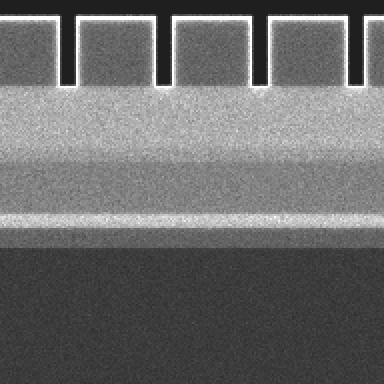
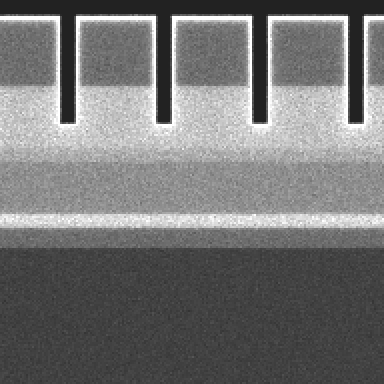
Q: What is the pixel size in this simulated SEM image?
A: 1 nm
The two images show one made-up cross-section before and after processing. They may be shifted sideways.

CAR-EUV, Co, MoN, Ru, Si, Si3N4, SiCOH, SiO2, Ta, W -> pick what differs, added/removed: Ru removed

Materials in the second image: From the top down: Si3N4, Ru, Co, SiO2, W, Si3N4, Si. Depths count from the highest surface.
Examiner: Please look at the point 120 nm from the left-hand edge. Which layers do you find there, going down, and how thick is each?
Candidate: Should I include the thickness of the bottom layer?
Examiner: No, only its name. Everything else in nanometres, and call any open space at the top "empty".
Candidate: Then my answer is Si3N4 70, Ru 62, Co 14, SiO2 52, W 14, Si3N4 20, Si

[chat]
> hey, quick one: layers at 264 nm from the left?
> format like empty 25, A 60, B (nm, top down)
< empty 108, Ru 24, Co 14, SiO2 52, W 14, Si3N4 20, Si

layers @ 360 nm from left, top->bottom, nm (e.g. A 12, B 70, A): empty 108, Ru 24, Co 14, SiO2 52, W 14, Si3N4 20, Si